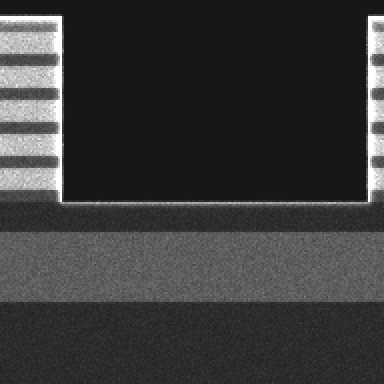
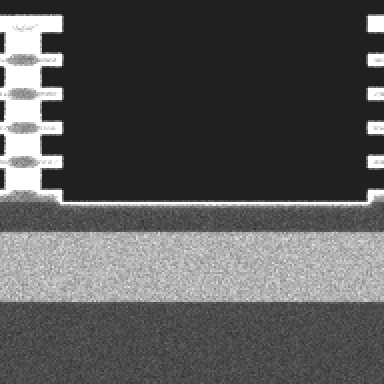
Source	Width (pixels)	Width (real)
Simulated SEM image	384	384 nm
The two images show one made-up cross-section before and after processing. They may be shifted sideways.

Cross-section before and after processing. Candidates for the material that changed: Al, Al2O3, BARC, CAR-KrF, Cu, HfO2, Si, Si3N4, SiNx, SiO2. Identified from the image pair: HfO2 (removed).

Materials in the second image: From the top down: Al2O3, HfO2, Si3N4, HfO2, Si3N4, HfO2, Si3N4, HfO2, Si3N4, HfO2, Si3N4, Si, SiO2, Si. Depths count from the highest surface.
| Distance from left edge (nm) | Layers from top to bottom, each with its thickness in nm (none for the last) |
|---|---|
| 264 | empty 186, Si 30, SiO2 70, Si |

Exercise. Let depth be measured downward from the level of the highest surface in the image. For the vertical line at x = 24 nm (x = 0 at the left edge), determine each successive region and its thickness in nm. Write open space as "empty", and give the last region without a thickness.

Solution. Al2O3 16, HfO2 22, Si3N4 12, HfO2 22, Si3N4 12, HfO2 22, Si3N4 12, HfO2 22, Si3N4 12, HfO2 22, Si3N4 12, Si 30, SiO2 70, Si